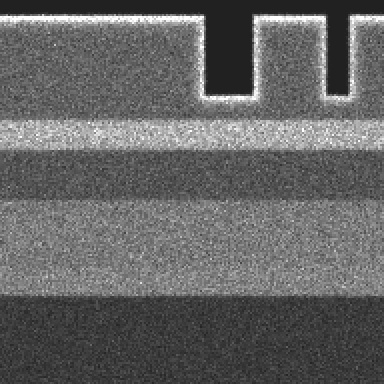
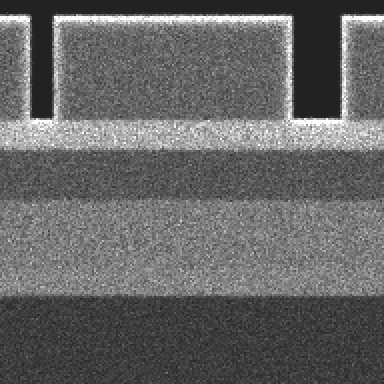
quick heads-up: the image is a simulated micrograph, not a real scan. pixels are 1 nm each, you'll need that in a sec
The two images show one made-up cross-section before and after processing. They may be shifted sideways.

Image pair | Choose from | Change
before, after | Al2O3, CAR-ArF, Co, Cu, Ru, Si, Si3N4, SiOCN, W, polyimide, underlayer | underlayer (removed)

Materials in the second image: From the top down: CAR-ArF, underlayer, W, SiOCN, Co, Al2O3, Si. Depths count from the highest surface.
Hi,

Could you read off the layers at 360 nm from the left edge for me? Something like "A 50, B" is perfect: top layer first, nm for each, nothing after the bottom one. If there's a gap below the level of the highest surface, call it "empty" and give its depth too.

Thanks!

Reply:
CAR-ArF 80, underlayer 24, W 30, SiOCN 50, Co 68, Al2O3 28, Si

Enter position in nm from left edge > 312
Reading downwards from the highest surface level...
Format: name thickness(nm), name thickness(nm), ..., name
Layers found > empty 104, W 30, SiOCN 50, Co 68, Al2O3 28, Si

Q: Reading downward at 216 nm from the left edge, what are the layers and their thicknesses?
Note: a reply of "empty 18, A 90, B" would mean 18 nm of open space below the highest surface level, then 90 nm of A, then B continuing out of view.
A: CAR-ArF 80, underlayer 24, W 30, SiOCN 50, Co 68, Al2O3 28, Si